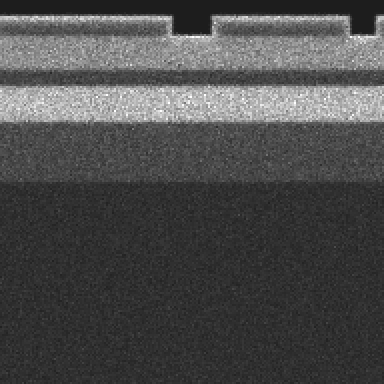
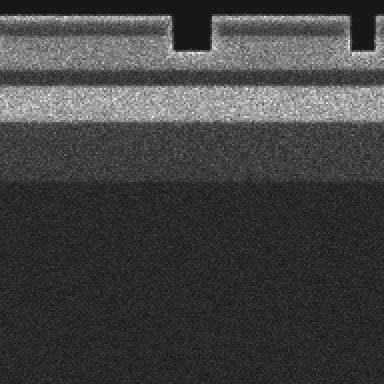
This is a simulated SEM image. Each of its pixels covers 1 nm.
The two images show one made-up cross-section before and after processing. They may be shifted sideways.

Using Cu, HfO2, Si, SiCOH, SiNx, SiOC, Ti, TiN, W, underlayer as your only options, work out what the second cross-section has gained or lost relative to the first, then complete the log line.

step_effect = removed W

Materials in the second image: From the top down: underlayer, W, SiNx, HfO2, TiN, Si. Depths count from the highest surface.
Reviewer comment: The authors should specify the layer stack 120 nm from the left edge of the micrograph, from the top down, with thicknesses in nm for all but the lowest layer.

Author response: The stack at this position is underlayer 20, W 34, SiNx 16, HfO2 36, TiN 60, Si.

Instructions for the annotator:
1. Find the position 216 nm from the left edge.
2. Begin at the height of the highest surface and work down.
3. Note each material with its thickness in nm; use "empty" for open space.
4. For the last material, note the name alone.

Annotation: underlayer 20, W 34, SiNx 16, HfO2 36, TiN 60, Si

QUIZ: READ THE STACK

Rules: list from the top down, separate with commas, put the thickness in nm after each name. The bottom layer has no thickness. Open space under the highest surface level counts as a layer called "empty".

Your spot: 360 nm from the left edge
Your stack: empty 36, W 18, SiNx 16, HfO2 36, TiN 60, Si